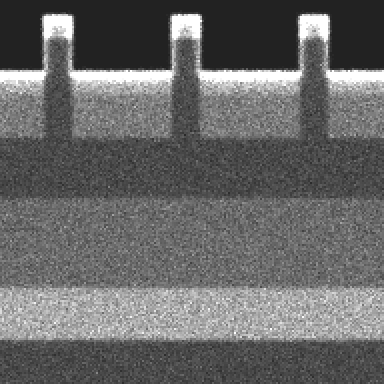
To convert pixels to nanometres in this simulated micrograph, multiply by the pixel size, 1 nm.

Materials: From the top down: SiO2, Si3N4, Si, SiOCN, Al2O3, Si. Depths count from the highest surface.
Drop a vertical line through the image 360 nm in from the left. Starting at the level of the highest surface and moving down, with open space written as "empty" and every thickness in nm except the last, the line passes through empty 56, SiO2 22, Si3N4 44, Si 60, SiOCN 90, Al2O3 52, Si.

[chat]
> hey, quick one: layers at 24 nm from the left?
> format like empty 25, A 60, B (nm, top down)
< empty 56, SiO2 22, Si3N4 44, Si 60, SiOCN 90, Al2O3 52, Si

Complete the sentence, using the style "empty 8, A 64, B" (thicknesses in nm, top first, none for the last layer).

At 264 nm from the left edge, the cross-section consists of empty 56, SiO2 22, Si3N4 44, Si 60, SiOCN 90, Al2O3 52, Si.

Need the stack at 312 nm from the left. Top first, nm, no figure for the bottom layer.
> SiO2 22, Si 160, SiOCN 90, Al2O3 52, Si